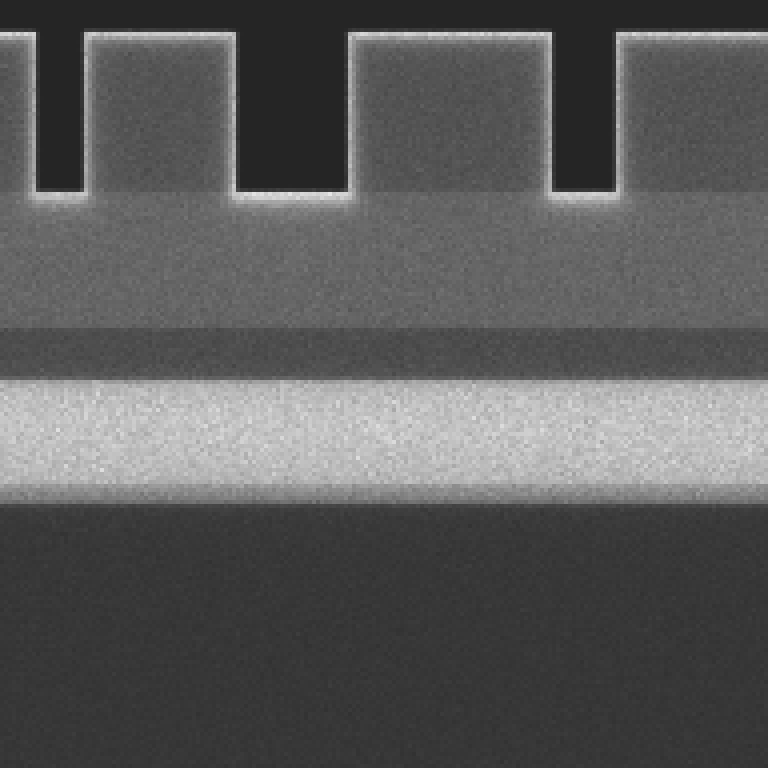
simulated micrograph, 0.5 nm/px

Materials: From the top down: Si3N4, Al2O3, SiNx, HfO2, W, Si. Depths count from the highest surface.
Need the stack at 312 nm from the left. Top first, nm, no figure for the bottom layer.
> Si3N4 80, Al2O3 68, SiNx 26, HfO2 52, W 10, Si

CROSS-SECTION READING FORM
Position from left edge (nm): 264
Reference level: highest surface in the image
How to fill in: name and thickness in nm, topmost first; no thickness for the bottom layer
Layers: Si3N4 80, Al2O3 68, SiNx 26, HfO2 52, W 10, Si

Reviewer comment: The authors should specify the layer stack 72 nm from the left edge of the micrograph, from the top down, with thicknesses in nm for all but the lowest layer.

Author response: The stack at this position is Si3N4 80, Al2O3 68, SiNx 26, HfO2 52, W 10, Si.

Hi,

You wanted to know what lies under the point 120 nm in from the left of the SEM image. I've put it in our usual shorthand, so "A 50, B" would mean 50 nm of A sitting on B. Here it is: empty 80, Al2O3 68, SiNx 26, HfO2 52, W 10, Si